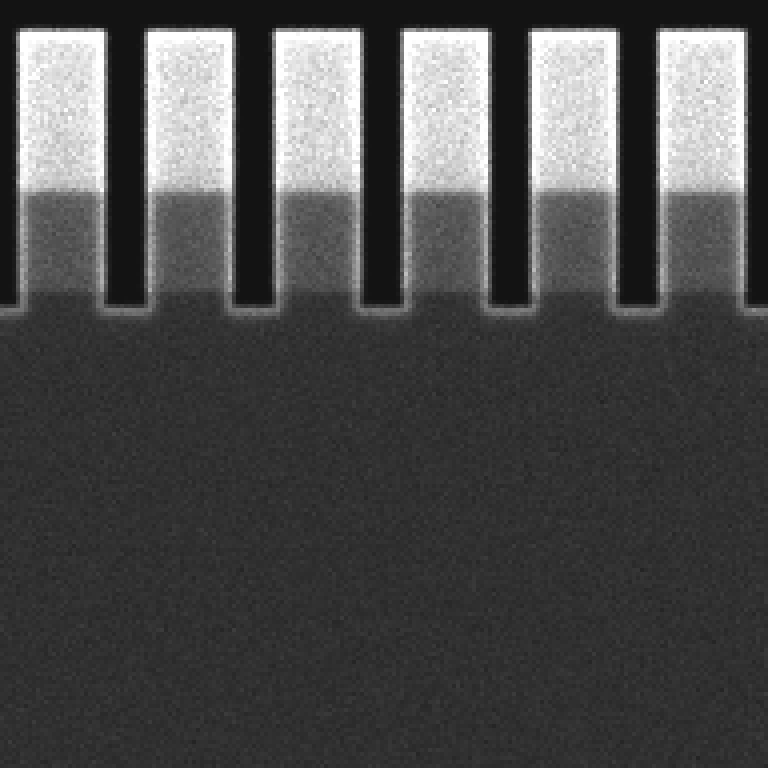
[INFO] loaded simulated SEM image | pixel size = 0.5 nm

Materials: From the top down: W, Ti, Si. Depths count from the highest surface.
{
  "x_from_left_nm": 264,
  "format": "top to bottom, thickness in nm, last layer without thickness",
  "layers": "empty 138, Si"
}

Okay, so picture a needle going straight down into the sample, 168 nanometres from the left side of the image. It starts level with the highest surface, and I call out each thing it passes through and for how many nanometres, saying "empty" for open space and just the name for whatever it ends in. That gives W 80, Ti 50, Si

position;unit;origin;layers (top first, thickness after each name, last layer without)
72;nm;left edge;empty 138, Si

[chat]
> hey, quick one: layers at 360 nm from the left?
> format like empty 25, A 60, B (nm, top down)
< W 80, Ti 50, Si